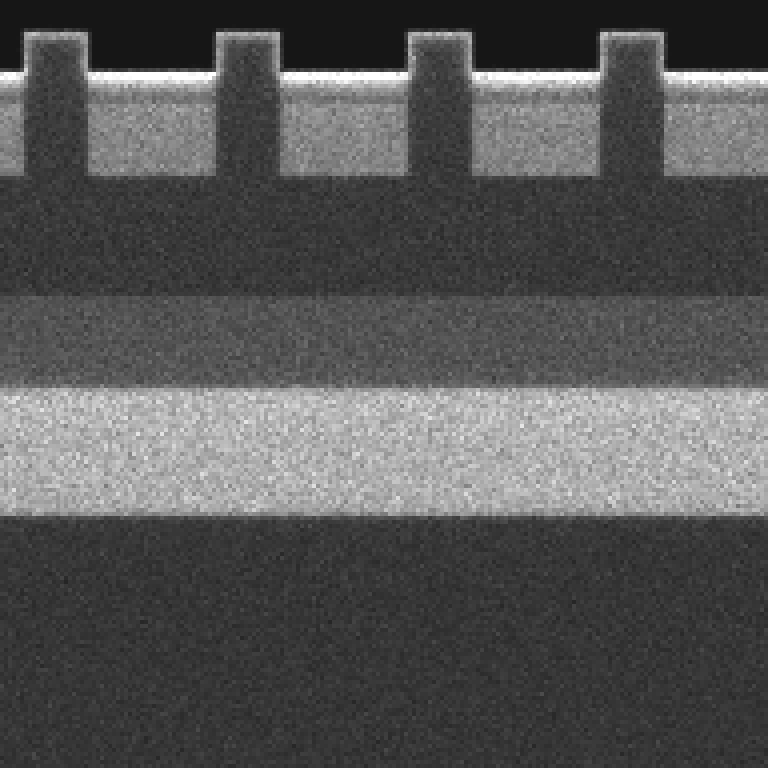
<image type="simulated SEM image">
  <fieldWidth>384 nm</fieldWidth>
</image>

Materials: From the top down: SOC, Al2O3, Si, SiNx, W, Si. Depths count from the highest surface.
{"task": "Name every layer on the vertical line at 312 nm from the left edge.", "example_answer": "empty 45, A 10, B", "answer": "Si 132, SiNx 46, W 64, Si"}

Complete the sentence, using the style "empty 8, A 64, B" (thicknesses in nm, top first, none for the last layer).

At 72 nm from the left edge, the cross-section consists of empty 20, SOC 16, Al2O3 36, Si 60, SiNx 46, W 64, Si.